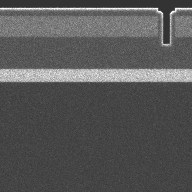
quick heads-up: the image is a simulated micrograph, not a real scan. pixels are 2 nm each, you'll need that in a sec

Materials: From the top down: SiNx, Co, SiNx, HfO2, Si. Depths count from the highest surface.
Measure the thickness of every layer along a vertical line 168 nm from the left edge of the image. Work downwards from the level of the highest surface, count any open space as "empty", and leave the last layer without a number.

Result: SiNx 16, Co 42, SiNx 64, HfO2 26, Si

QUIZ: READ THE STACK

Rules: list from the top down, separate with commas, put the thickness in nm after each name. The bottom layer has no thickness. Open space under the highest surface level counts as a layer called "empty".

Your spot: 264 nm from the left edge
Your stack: SiNx 16, Co 42, SiNx 64, HfO2 26, Si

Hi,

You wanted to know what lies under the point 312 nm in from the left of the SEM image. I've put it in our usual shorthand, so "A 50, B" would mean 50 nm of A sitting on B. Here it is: SiNx 16, Co 42, SiNx 64, HfO2 26, Si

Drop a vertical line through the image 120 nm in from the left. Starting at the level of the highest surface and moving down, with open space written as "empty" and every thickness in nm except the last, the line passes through SiNx 16, Co 42, SiNx 64, HfO2 26, Si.